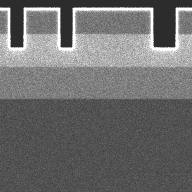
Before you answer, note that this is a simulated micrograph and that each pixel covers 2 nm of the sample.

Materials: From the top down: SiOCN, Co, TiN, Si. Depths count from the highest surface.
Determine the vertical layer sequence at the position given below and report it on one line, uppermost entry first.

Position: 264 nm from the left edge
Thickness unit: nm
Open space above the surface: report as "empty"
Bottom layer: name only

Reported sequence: SiOCN 52, Co 66, TiN 64, Si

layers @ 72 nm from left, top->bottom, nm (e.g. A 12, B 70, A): SiOCN 52, Co 66, TiN 64, Si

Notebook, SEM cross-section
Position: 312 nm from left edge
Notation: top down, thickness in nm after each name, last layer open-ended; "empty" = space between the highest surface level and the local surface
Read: empty 80, Co 38, TiN 64, Si